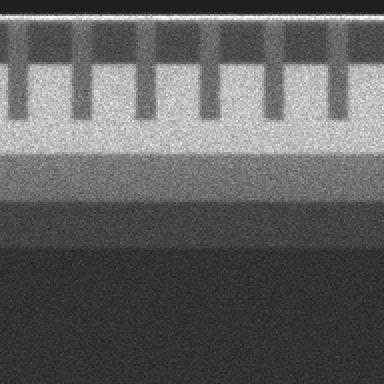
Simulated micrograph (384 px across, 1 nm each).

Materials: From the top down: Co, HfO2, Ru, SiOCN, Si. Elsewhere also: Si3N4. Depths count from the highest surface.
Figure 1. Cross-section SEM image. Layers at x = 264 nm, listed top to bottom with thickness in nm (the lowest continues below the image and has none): Co 104, HfO2 34, Ru 48, SiOCN 46, Si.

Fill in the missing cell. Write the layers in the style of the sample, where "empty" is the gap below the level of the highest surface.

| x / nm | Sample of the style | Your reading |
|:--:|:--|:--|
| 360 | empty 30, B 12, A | Si3N4 48, HfO2 90, Ru 48, SiOCN 46, Si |